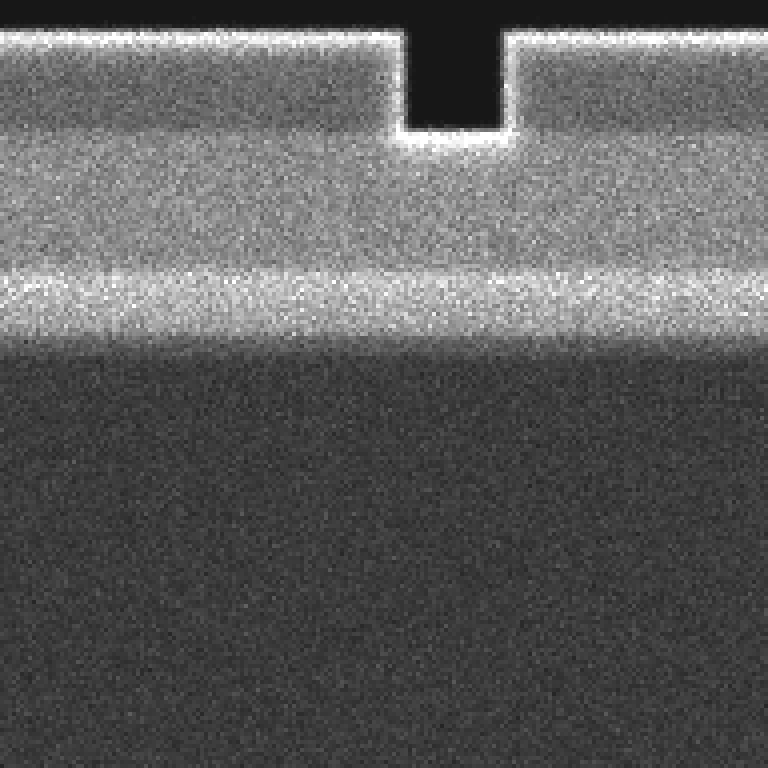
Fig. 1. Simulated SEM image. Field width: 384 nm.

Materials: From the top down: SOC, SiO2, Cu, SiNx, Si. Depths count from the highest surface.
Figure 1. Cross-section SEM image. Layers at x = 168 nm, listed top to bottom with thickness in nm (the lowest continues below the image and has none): SOC 50, SiO2 70, Cu 32, SiNx 10, Si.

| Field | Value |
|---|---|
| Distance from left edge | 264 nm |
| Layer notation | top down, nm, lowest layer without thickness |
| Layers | SOC 50, SiO2 70, Cu 32, SiNx 10, Si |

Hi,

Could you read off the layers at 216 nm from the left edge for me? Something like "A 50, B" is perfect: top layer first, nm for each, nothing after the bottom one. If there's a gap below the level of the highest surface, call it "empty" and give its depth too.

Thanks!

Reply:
empty 50, SiO2 70, Cu 32, SiNx 10, Si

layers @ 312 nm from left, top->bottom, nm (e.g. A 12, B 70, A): SOC 50, SiO2 70, Cu 32, SiNx 10, Si